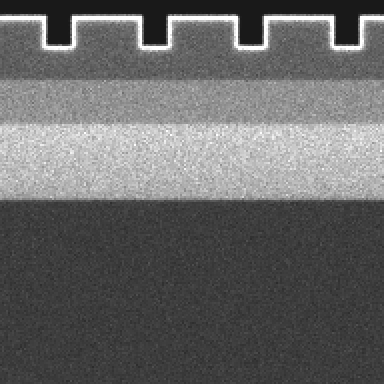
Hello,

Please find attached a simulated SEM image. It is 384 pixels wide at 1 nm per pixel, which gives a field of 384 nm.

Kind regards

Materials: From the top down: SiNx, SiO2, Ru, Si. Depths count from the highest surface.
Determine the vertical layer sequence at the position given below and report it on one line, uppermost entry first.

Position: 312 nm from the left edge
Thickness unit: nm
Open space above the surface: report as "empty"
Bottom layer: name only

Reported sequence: SiNx 64, SiO2 44, Ru 76, Si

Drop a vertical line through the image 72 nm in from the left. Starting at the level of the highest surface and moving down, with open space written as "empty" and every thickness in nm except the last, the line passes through SiNx 64, SiO2 44, Ru 76, Si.